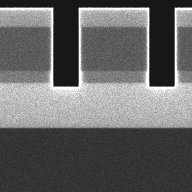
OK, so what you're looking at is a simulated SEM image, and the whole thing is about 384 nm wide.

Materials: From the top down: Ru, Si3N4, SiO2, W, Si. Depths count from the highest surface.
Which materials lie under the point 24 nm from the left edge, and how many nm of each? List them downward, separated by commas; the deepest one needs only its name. Ru 38, Si3N4 88, SiO2 24, W 90, Si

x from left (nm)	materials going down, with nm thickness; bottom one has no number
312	empty 158, W 82, Si